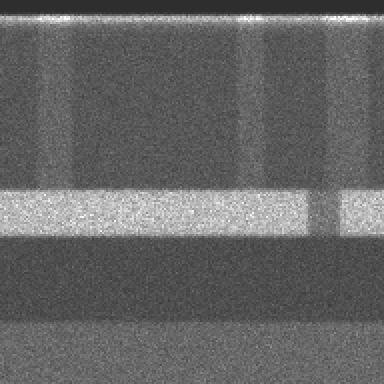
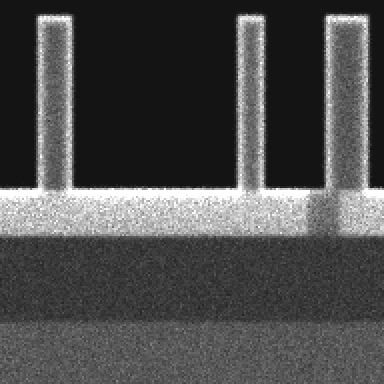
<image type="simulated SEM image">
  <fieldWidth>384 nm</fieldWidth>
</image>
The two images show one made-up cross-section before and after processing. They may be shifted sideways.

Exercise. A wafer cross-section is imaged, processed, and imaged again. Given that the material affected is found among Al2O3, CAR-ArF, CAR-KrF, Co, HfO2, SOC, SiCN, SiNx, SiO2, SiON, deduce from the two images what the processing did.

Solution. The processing removed SOC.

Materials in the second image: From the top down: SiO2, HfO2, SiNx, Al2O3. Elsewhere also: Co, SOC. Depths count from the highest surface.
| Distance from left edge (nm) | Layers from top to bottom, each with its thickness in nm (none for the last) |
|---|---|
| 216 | empty 174, HfO2 46, SiNx 86, Al2O3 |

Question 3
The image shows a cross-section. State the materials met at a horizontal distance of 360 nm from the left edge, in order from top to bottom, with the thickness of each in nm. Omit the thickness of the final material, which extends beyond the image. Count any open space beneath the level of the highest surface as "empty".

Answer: SiO2 174, HfO2 46, SiNx 86, Al2O3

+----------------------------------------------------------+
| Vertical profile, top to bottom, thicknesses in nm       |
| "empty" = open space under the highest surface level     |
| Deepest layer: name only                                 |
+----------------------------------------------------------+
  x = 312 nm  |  empty 174, Co 46, SiNx 86, Al2O3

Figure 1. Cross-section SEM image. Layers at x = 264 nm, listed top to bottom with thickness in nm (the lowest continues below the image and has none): empty 174, HfO2 46, SiNx 86, Al2O3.